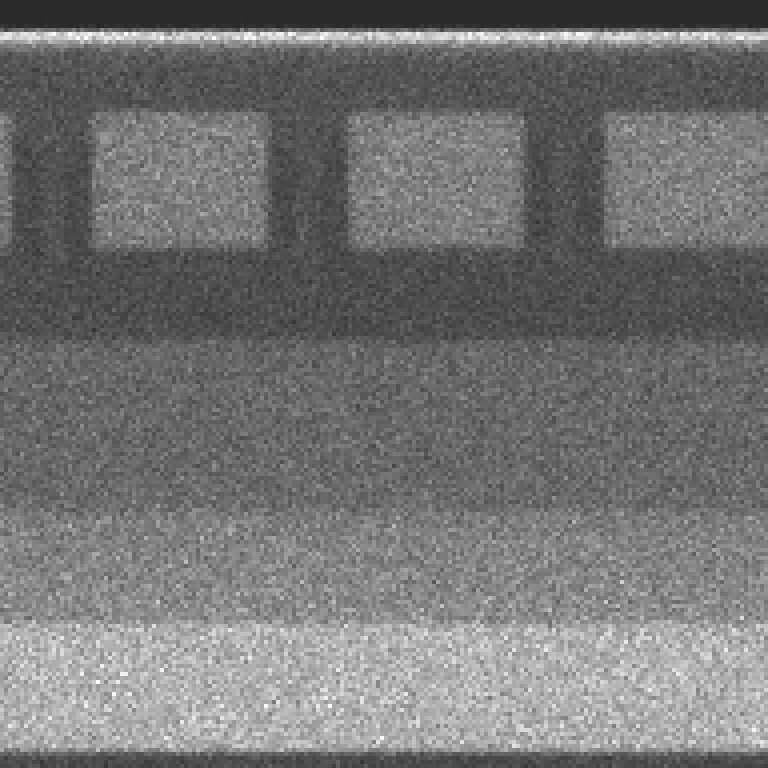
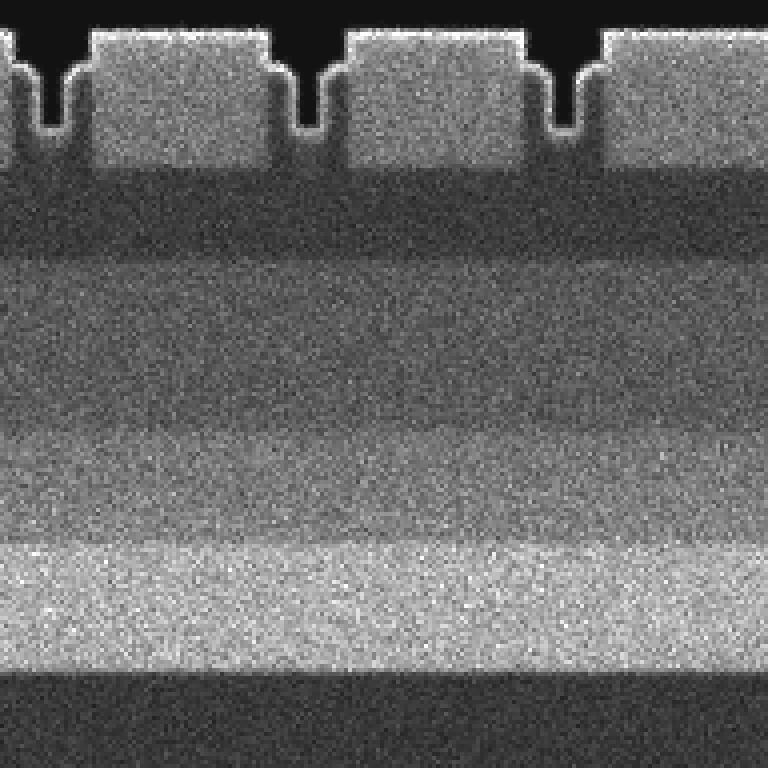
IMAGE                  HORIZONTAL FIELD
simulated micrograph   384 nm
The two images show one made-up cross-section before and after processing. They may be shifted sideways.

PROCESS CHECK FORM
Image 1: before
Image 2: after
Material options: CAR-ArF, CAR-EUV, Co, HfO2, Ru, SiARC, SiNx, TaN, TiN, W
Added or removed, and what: removed, SiARC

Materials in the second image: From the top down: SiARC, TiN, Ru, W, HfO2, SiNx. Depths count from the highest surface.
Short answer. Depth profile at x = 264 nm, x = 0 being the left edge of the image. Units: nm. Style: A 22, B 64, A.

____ empty 16, SiNx 60, TiN 38, Ru 86, W 56, HfO2 64, SiNx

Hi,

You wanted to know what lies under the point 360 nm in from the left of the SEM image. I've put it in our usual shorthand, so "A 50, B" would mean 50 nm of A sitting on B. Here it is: W 68, TiN 46, Ru 86, W 56, HfO2 64, SiNx